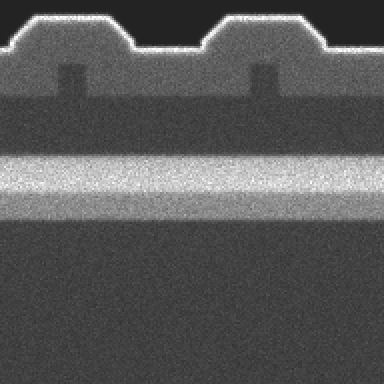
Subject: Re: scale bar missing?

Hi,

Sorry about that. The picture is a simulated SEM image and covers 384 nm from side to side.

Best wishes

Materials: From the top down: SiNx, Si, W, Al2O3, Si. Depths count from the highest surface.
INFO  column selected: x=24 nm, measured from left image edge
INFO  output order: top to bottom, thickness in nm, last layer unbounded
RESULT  empty 10, SiNx 70, Si 60, W 36, Al2O3 28, Si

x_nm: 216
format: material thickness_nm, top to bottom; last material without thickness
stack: empty 10, SiNx 70, Si 60, W 36, Al2O3 28, Si